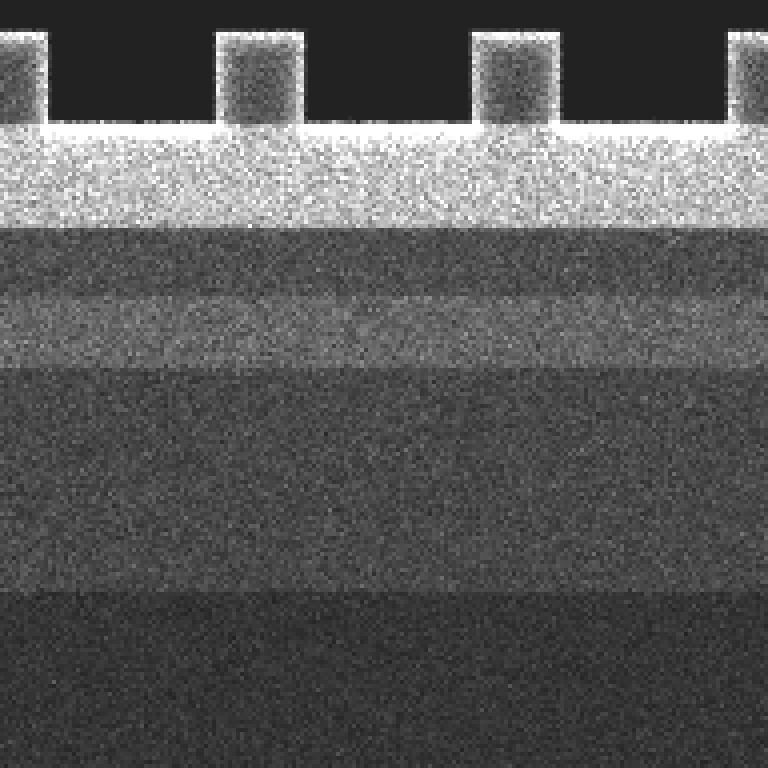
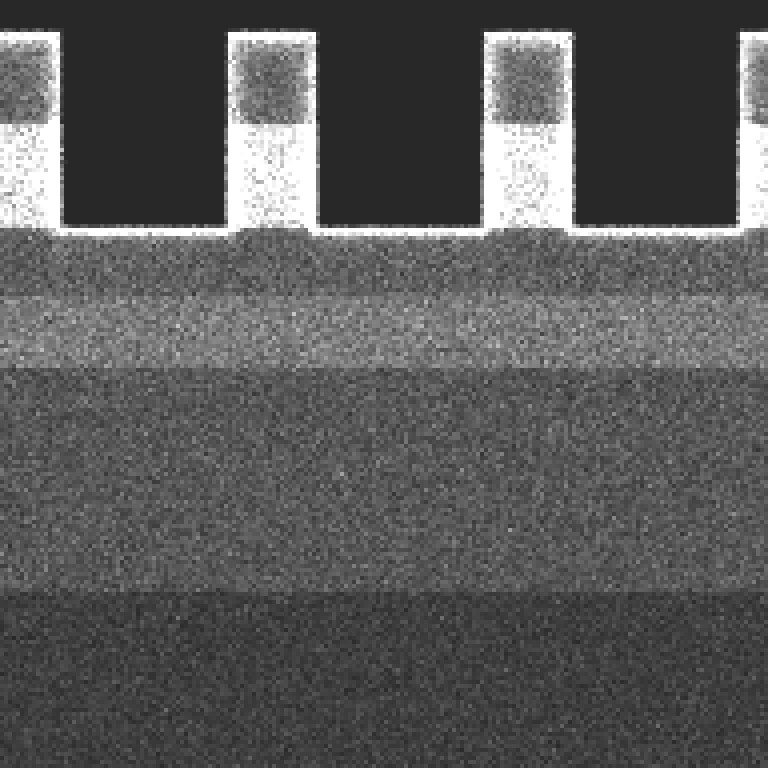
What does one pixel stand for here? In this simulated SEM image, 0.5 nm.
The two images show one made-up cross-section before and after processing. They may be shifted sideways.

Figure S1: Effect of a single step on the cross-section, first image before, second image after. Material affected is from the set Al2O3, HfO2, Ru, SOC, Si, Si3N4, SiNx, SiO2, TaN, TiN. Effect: removed HfO2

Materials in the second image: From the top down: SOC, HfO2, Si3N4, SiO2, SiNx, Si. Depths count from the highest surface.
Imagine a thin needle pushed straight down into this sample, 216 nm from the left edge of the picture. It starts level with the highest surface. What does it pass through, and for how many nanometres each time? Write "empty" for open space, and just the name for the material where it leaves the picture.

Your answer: empty 98, Si3N4 34, SiO2 36, SiNx 112, Si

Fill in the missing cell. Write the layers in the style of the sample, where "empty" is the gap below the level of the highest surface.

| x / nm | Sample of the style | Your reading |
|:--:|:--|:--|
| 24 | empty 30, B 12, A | SOC 46, HfO2 52, Si3N4 34, SiO2 36, SiNx 112, Si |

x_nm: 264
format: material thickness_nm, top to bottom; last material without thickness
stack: SOC 46, HfO2 52, Si3N4 34, SiO2 36, SiNx 112, Si